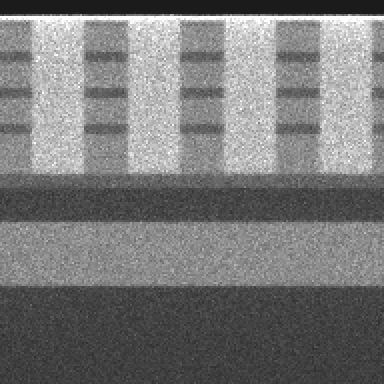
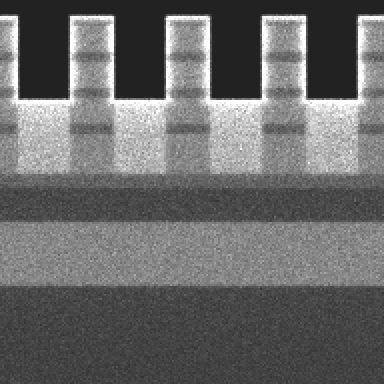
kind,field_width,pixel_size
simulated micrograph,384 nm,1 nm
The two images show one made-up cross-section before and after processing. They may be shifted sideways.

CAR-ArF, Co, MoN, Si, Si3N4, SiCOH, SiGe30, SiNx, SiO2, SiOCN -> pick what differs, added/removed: Co removed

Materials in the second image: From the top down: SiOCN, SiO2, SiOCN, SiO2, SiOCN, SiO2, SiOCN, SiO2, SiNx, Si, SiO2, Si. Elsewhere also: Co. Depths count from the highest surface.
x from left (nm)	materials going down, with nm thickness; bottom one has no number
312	empty 84, Co 74, SiNx 14, Si 34, SiO2 64, Si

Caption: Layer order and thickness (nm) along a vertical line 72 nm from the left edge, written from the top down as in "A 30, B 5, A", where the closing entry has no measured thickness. SiOCN 10, SiO2 26, SiOCN 10, SiO2 26, SiOCN 10, SiO2 26, SiOCN 10, SiO2 40, SiNx 14, Si 34, SiO2 64, Si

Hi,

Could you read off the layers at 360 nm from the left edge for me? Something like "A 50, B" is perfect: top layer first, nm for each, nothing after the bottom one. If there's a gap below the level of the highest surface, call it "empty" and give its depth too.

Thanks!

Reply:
SiOCN 10, SiO2 26, SiOCN 10, SiO2 26, SiOCN 10, SiO2 26, SiOCN 10, SiO2 40, SiNx 14, Si 34, SiO2 64, Si